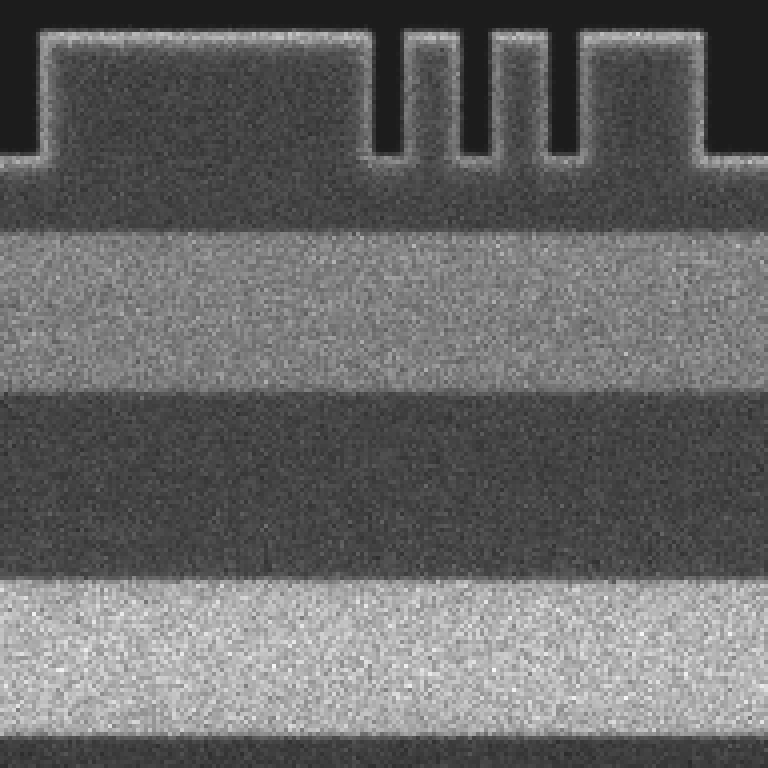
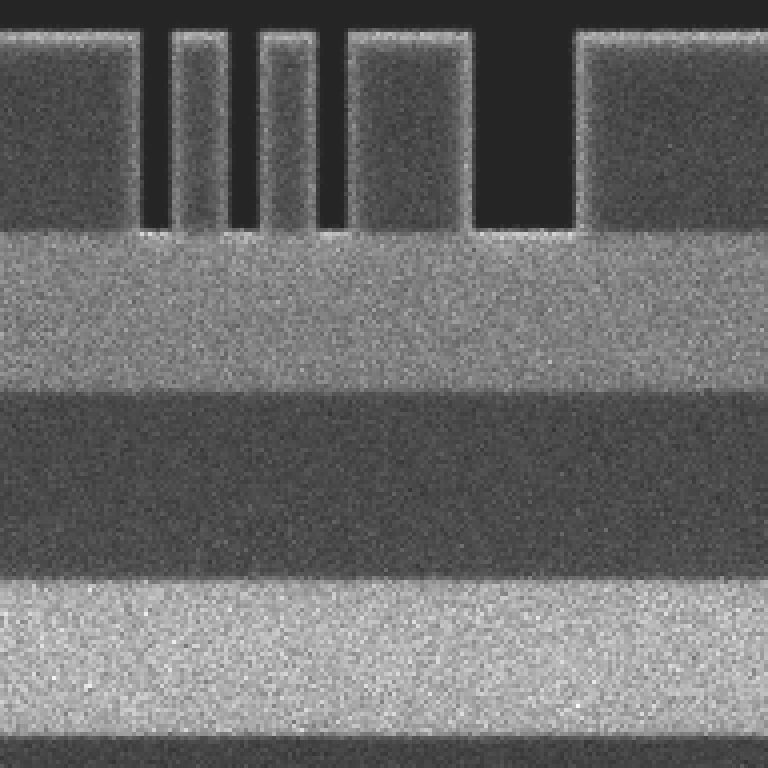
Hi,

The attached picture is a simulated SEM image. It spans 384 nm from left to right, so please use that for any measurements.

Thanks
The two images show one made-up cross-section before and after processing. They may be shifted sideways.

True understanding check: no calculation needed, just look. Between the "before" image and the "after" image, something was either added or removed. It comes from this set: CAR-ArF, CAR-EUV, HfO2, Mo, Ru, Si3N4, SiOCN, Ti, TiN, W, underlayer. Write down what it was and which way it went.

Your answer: underlayer (removed)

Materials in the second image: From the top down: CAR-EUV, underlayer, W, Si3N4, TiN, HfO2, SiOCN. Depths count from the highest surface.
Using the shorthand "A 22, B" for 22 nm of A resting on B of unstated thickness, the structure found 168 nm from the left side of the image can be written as empty 100, W 80, Si3N4 54, TiN 40, HfO2 78, SiOCN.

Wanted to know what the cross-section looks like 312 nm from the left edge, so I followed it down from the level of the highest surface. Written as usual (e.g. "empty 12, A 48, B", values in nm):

CAR-EUV 62, underlayer 38, W 80, Si3N4 54, TiN 40, HfO2 78, SiOCN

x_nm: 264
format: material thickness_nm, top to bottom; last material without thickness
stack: empty 100, W 80, Si3N4 54, TiN 40, HfO2 78, SiOCN